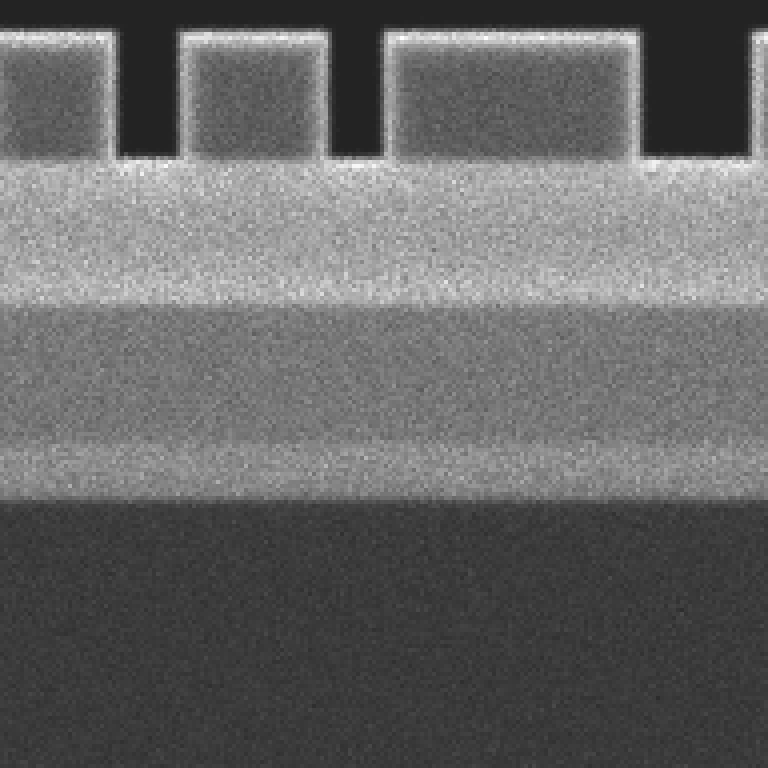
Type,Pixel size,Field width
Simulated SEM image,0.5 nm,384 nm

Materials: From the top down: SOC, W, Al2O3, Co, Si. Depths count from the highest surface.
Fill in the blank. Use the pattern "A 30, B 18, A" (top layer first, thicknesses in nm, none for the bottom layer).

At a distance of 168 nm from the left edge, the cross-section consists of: empty 64, W 72, Al2O3 70, Co 28, Si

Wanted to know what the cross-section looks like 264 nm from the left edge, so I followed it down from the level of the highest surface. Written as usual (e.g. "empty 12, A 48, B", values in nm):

SOC 64, W 72, Al2O3 70, Co 28, Si